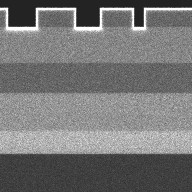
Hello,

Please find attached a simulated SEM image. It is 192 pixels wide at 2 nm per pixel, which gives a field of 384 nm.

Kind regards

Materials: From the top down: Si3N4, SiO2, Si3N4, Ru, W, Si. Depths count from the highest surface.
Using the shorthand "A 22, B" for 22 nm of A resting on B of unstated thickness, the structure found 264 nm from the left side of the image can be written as Si3N4 38, SiO2 72, Si3N4 60, Ru 76, W 46, Si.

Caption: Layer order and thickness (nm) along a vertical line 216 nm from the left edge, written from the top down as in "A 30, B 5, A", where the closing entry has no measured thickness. Si3N4 38, SiO2 72, Si3N4 60, Ru 76, W 46, Si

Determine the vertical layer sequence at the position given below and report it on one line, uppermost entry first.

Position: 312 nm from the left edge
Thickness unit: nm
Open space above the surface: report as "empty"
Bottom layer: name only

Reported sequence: Si3N4 38, SiO2 72, Si3N4 60, Ru 76, W 46, Si